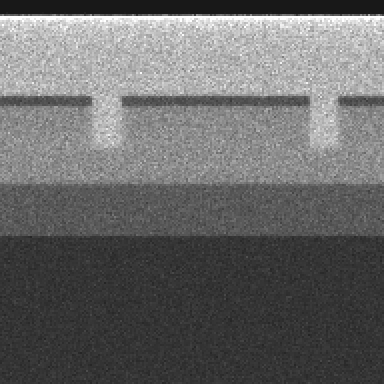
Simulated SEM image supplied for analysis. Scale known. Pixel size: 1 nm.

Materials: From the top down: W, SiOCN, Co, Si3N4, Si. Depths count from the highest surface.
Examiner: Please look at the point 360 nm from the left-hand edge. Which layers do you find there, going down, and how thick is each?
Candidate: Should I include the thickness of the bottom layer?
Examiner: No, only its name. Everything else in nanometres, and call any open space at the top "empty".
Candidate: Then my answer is W 80, SiOCN 10, Co 78, Si3N4 52, Si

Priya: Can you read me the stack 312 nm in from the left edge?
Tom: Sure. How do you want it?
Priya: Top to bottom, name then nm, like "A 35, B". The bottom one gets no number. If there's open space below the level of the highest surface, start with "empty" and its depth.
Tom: W 132, Co 36, Si3N4 52, Si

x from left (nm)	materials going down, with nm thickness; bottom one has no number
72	W 80, SiOCN 10, Co 78, Si3N4 52, Si